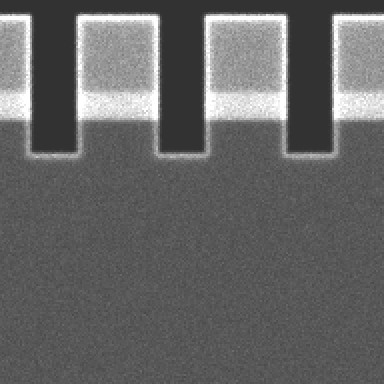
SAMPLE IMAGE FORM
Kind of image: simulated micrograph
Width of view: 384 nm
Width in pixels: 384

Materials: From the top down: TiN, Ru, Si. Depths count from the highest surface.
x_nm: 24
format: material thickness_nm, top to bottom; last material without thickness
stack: TiN 76, Ru 28, Si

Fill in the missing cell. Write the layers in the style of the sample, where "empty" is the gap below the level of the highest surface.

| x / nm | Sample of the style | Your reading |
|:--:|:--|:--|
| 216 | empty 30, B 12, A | TiN 76, Ru 28, Si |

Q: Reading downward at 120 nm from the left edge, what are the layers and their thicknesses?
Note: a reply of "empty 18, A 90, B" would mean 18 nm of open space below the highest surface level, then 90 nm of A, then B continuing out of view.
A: TiN 76, Ru 28, Si